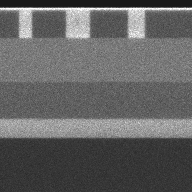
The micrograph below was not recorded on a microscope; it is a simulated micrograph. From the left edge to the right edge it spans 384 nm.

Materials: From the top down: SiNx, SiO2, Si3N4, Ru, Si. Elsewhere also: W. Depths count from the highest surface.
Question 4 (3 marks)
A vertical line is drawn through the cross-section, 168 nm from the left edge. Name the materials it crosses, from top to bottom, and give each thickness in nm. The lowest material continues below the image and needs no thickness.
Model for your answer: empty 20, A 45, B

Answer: W 60, SiO2 88, Si3N4 74, Ru 38, Si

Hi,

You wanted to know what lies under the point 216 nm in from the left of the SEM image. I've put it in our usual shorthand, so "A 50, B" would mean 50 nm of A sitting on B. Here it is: SiNx 60, SiO2 88, Si3N4 74, Ru 38, Si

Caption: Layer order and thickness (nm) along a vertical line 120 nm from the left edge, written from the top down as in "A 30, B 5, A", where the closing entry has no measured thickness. SiNx 60, SiO2 88, Si3N4 74, Ru 38, Si